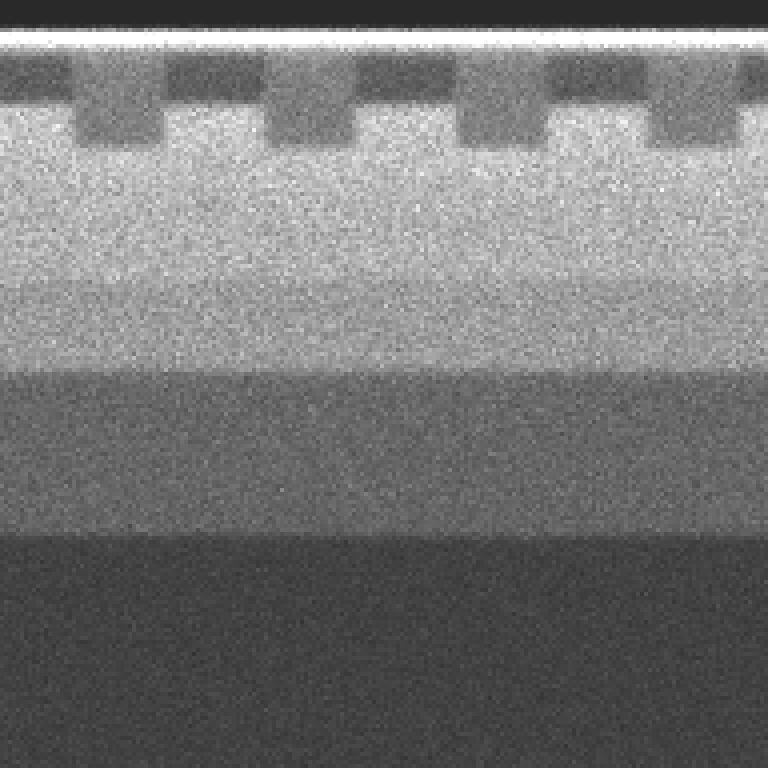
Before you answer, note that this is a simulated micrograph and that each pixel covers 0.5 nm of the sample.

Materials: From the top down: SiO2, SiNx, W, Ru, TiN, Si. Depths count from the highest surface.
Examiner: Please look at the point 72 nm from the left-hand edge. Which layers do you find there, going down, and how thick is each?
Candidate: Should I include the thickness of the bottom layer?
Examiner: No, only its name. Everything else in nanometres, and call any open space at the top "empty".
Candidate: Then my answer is SiO2 58, W 66, Ru 46, TiN 82, Si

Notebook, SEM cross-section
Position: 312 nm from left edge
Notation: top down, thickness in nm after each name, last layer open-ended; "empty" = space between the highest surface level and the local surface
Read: SiO2 10, SiNx 26, W 88, Ru 46, TiN 82, Si